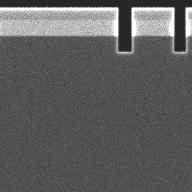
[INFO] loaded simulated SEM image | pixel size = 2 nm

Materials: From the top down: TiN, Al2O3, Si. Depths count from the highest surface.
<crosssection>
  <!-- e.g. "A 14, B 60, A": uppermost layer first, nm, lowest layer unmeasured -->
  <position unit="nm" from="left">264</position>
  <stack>TiN 24, Al2O3 32, Si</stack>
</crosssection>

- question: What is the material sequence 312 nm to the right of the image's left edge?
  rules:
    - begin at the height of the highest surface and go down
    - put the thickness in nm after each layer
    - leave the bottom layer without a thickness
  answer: TiN 24, Al2O3 32, Si